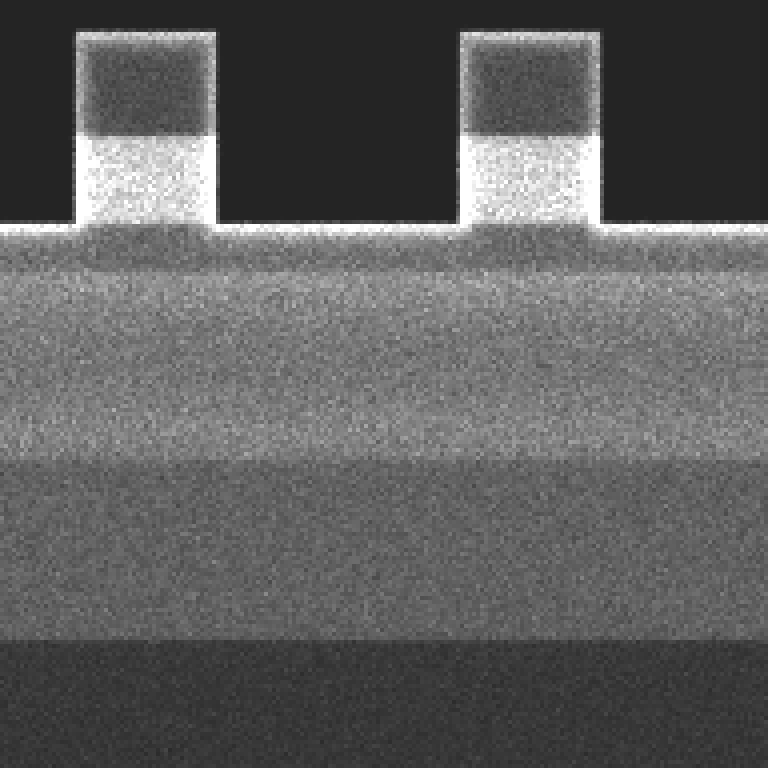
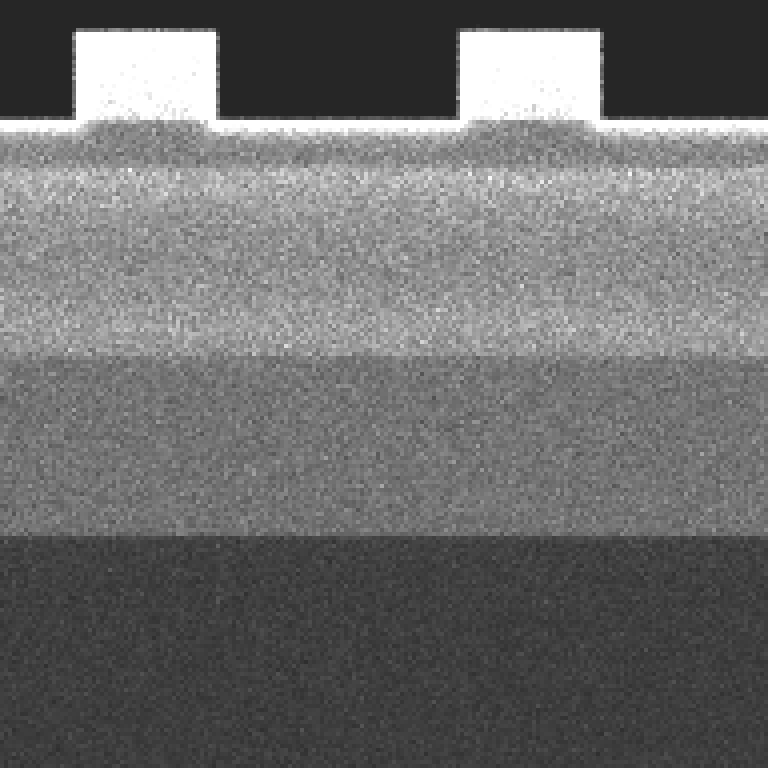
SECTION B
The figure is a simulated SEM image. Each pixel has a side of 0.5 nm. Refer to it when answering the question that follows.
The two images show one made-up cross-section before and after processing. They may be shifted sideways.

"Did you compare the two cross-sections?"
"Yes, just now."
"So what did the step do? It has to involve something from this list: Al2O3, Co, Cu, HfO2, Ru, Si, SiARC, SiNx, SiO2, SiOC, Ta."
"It removed SiARC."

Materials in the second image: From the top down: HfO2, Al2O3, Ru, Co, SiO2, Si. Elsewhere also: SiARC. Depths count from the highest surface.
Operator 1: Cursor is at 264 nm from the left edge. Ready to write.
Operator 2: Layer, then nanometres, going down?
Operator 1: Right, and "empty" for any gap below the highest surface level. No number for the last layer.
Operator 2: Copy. HfO2 44, Al2O3 24, Ru 82, Co 12, SiO2 90, Si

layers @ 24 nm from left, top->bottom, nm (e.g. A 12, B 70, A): empty 44, Al2O3 24, Ru 82, Co 12, SiO2 90, Si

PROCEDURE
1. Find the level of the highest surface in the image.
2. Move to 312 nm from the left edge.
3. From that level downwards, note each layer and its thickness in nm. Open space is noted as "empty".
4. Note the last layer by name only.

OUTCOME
empty 44, Al2O3 24, Ru 82, Co 12, SiO2 90, Si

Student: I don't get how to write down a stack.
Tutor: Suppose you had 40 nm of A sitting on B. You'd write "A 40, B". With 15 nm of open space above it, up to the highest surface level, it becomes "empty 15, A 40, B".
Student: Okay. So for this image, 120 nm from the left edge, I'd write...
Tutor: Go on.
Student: empty 44, Al2O3 24, Ru 82, Co 12, SiO2 90, Si